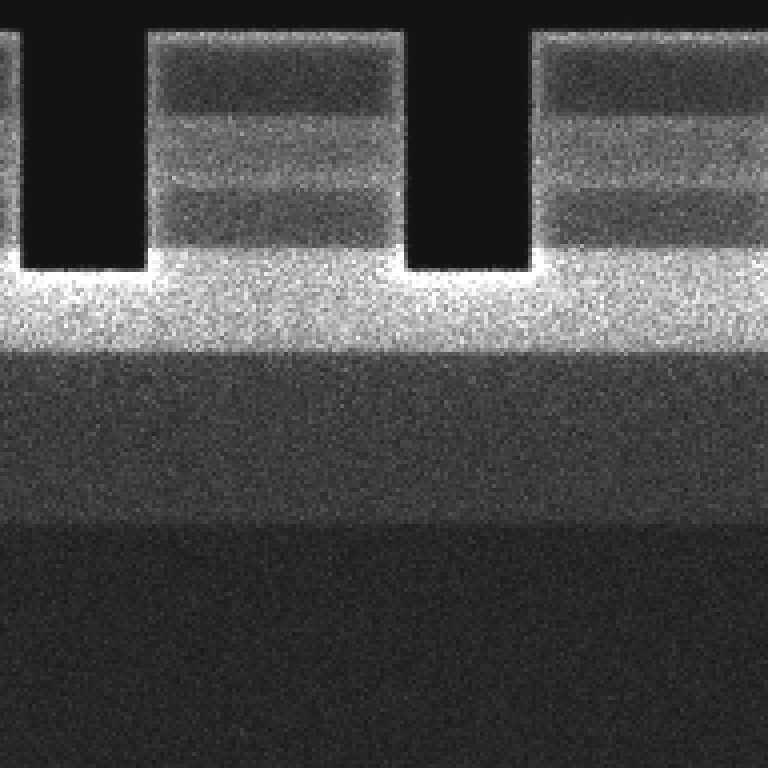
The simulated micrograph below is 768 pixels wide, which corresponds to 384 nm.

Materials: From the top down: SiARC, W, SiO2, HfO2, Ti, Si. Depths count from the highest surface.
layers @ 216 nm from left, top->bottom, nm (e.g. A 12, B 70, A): empty 120, HfO2 40, Ti 86, Si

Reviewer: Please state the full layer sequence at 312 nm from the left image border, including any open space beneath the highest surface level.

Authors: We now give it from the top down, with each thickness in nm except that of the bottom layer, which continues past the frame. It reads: SiARC 42, W 36, SiO2 30, HfO2 52, Ti 86, Si